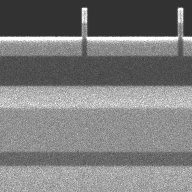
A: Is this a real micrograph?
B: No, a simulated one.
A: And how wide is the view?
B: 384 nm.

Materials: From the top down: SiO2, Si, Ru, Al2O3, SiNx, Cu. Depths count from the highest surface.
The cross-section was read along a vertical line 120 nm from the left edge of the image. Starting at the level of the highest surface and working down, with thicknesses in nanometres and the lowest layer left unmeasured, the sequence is empty 58, SiO2 38, Si 60, Ru 44, Al2O3 88, SiNx 28, Cu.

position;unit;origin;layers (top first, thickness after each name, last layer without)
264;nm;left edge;empty 58, SiO2 38, Si 60, Ru 44, Al2O3 88, SiNx 28, Cu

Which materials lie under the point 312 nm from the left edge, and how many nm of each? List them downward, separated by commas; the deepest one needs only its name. empty 58, SiO2 38, Si 60, Ru 44, Al2O3 88, SiNx 28, Cu